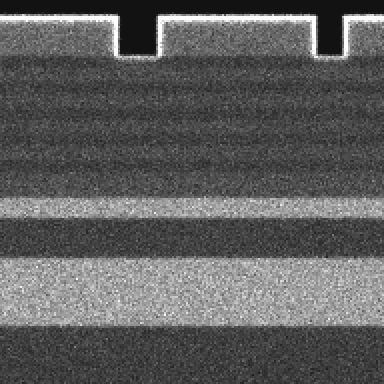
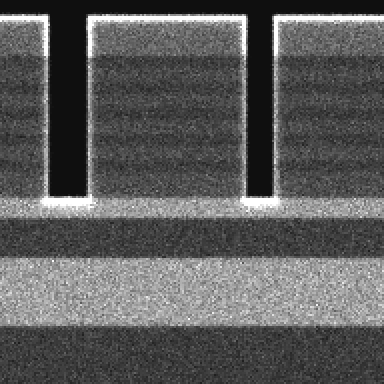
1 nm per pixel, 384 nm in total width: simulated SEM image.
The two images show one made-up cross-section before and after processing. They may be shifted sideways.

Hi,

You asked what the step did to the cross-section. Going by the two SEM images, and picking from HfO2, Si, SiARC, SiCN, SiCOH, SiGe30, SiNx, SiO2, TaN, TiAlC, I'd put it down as Si and SiGe30, removed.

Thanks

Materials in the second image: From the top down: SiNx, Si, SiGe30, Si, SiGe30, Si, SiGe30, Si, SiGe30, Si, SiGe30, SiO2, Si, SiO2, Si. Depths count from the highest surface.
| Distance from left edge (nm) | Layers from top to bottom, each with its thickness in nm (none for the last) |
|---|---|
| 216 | SiNx 40, Si 12, SiGe30 14, Si 12, SiGe30 14, Si 12, SiGe30 14, Si 12, SiGe30 14, Si 12, SiGe30 26, SiO2 20, Si 40, SiO2 68, Si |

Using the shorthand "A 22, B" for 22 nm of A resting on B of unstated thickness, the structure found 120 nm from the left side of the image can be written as SiNx 40, Si 12, SiGe30 14, Si 12, SiGe30 14, Si 12, SiGe30 14, Si 12, SiGe30 14, Si 12, SiGe30 26, SiO2 20, Si 40, SiO2 68, Si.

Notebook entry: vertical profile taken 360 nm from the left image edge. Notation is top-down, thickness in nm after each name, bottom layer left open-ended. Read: SiNx 40, Si 12, SiGe30 14, Si 12, SiGe30 14, Si 12, SiGe30 14, Si 12, SiGe30 14, Si 12, SiGe30 26, SiO2 20, Si 40, SiO2 68, Si